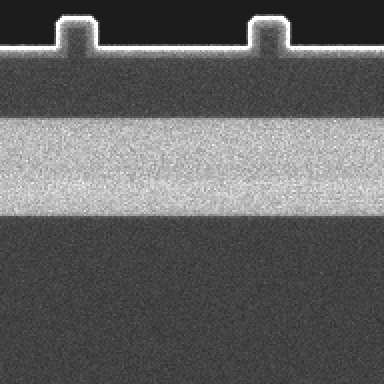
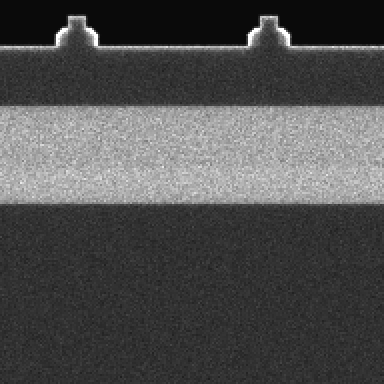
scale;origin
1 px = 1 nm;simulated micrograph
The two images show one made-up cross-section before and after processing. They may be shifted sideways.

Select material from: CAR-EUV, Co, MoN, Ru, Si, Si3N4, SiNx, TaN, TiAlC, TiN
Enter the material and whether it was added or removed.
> SiNx / removed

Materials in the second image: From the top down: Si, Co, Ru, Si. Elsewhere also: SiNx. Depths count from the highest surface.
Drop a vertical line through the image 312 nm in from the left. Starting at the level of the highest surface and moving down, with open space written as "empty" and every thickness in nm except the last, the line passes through empty 30, Si 60, Co 62, Ru 36, Si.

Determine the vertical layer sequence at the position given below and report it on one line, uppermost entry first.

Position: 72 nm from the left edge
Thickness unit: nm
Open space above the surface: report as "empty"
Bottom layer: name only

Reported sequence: Si 90, Co 62, Ru 36, Si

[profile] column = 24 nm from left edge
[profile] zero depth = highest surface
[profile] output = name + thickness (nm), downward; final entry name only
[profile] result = empty 30, Si 60, Co 62, Ru 36, Si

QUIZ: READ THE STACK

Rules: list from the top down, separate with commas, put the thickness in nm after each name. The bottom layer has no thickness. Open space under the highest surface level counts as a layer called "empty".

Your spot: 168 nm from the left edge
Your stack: empty 30, Si 60, Co 62, Ru 36, Si